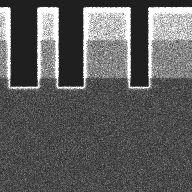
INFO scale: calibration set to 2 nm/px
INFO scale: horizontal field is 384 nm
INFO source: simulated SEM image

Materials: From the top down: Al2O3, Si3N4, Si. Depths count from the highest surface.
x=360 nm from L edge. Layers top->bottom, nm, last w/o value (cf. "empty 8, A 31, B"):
Al2O3 64, Si3N4 76, Si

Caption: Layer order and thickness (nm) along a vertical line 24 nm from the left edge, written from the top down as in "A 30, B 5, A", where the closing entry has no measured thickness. empty 158, Si